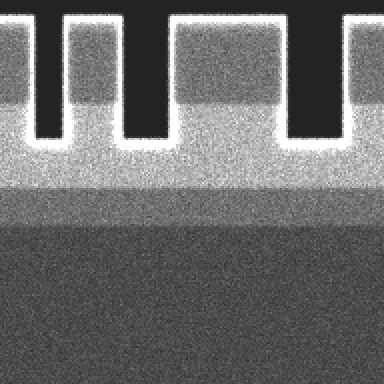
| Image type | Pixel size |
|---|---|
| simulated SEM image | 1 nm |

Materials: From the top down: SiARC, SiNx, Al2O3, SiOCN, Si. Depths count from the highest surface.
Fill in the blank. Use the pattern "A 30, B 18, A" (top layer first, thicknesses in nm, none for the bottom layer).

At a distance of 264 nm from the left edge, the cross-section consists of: SiARC 14, SiNx 74, Al2O3 84, SiOCN 38, Si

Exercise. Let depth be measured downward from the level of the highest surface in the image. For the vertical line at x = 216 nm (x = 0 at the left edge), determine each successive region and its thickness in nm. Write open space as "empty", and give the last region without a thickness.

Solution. SiARC 14, SiNx 74, Al2O3 84, SiOCN 38, Si